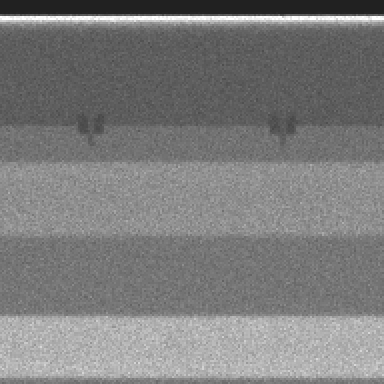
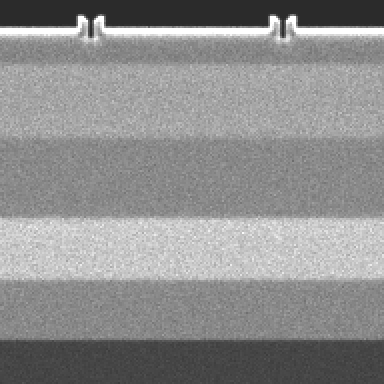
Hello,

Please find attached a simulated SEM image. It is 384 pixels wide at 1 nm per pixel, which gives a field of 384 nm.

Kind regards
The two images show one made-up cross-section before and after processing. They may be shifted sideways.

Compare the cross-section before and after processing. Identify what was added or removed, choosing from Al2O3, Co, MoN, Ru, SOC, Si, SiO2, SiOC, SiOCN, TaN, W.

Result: SOC removed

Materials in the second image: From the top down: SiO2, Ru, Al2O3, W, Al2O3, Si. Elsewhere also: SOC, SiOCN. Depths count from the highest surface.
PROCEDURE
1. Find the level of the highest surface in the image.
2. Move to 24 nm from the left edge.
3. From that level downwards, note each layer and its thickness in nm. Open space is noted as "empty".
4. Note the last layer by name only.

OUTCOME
empty 12, SiO2 36, Ru 74, Al2O3 80, W 62, Al2O3 60, Si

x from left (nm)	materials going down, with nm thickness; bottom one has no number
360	empty 12, SiO2 36, Ru 74, Al2O3 80, W 62, Al2O3 60, Si